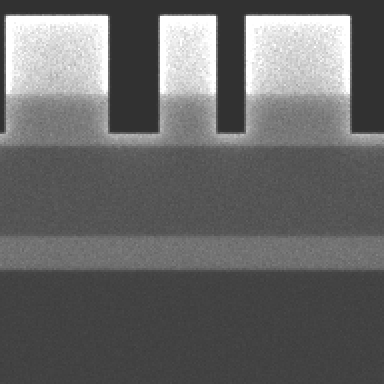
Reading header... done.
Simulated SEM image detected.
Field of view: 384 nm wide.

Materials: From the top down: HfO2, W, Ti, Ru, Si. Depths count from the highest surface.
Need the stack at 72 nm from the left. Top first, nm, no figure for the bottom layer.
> HfO2 78, W 52, Ti 90, Ru 34, Si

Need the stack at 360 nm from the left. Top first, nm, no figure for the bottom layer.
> empty 118, W 12, Ti 90, Ru 34, Si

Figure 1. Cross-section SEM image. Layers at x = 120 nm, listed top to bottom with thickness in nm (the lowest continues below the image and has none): empty 118, W 12, Ti 90, Ru 34, Si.